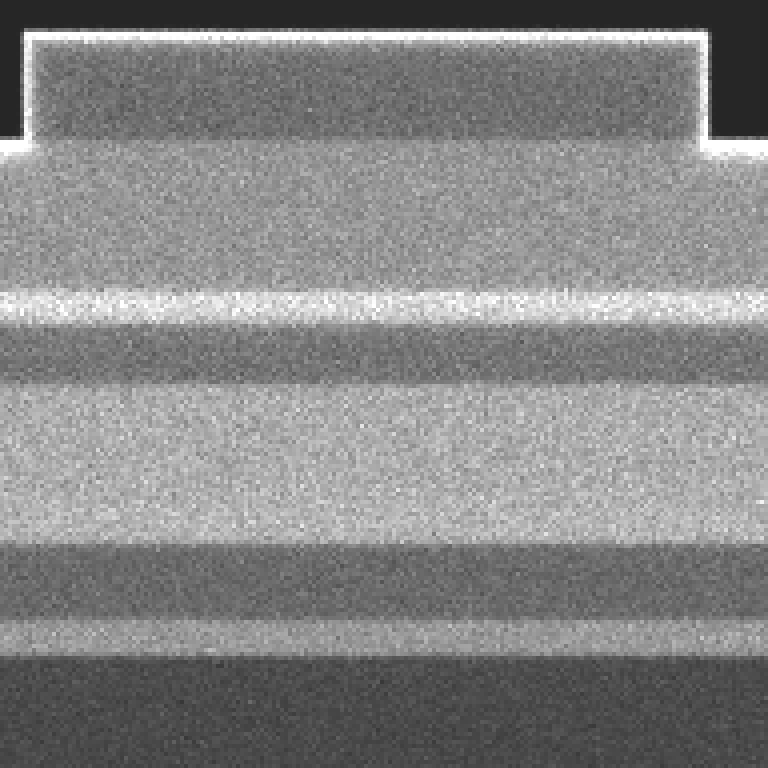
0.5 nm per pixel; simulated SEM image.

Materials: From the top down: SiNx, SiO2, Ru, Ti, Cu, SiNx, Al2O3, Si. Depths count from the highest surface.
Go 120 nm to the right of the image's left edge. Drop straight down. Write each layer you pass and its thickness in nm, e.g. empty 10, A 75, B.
SiNx 54, SiO2 76, Ru 16, Ti 30, Cu 80, SiNx 38, Al2O3 18, Si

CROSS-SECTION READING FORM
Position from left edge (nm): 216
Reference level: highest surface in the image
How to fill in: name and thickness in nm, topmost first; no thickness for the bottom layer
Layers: SiNx 54, SiO2 76, Ru 16, Ti 30, Cu 80, SiNx 38, Al2O3 18, Si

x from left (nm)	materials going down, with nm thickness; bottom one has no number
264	SiNx 54, SiO2 76, Ru 16, Ti 30, Cu 80, SiNx 38, Al2O3 18, Si